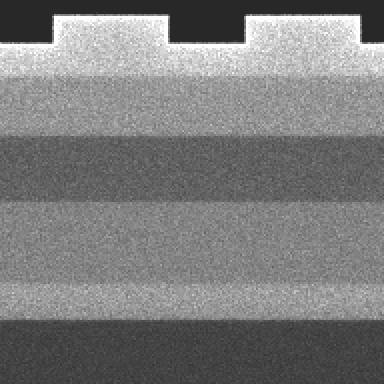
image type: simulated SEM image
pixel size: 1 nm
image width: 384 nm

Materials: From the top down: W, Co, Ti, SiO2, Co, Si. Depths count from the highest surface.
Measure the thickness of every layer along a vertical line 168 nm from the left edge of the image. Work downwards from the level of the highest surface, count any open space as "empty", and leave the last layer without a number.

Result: empty 28, W 32, Co 60, Ti 66, SiO2 82, Co 36, Si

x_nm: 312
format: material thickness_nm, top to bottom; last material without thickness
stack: W 60, Co 60, Ti 66, SiO2 82, Co 36, Si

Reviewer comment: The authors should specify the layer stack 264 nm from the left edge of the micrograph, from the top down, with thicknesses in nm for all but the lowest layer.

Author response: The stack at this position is W 60, Co 60, Ti 66, SiO2 82, Co 36, Si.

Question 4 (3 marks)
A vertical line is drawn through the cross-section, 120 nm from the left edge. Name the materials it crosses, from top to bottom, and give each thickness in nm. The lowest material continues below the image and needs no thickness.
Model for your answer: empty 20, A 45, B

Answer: W 60, Co 60, Ti 66, SiO2 82, Co 36, Si